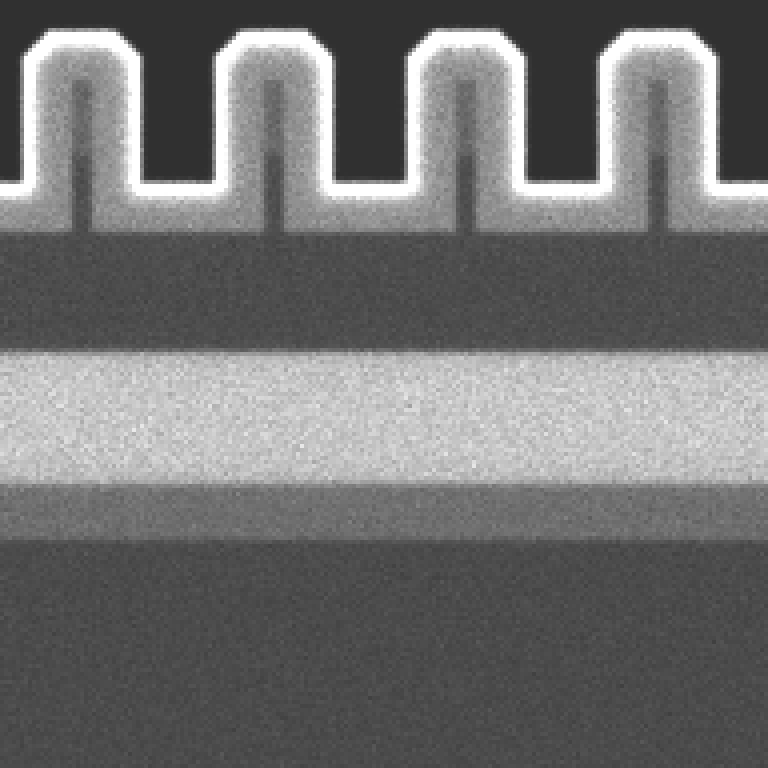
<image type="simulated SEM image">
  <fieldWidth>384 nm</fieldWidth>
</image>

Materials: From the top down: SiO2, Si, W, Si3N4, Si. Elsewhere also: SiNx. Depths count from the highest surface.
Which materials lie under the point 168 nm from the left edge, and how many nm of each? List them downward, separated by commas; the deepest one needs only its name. empty 76, SiO2 24, Si 60, W 66, Si3N4 28, Si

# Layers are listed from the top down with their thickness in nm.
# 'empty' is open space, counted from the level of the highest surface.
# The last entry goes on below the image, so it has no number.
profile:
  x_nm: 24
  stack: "SiO2 100, Si 60, W 66, Si3N4 28, Si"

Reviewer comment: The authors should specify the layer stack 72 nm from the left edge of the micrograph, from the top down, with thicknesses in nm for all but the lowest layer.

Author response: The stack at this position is empty 76, SiO2 24, Si 60, W 66, Si3N4 28, Si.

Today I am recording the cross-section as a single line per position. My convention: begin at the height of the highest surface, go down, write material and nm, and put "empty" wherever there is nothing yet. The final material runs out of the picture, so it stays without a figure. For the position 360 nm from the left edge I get empty 76, SiO2 24, Si 60, W 66, Si3N4 28, Si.